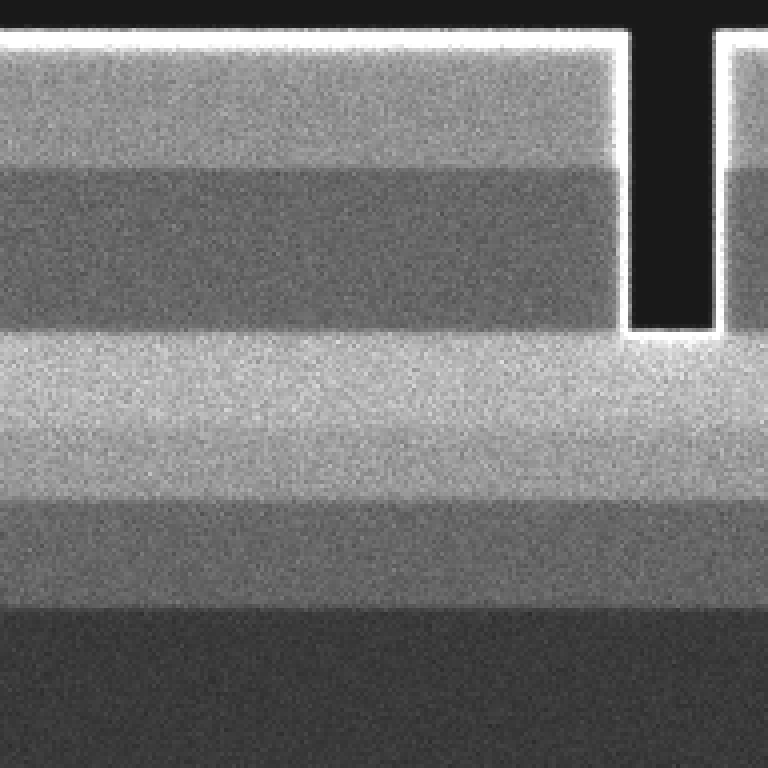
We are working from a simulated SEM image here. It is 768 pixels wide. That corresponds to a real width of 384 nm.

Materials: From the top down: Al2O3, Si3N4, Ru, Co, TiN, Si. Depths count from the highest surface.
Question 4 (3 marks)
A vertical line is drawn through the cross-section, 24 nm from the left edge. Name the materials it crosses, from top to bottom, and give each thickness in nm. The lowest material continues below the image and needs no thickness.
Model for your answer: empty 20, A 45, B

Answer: Al2O3 68, Si3N4 82, Ru 48, Co 36, TiN 54, Si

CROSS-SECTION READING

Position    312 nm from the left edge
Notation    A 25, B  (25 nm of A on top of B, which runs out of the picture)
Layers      Al2O3 68, Si3N4 82, Ru 48, Co 36, TiN 54, Si